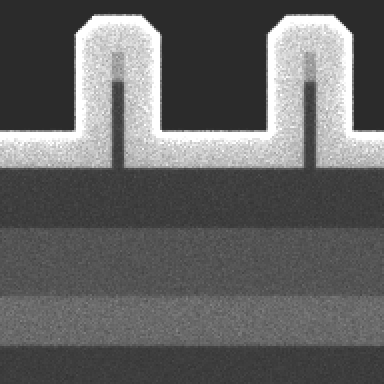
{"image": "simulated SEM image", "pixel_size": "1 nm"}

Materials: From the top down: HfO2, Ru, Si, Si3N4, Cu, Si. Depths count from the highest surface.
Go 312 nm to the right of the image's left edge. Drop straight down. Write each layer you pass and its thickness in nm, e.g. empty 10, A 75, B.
HfO2 36, Ru 30, Si 146, Si3N4 68, Cu 50, Si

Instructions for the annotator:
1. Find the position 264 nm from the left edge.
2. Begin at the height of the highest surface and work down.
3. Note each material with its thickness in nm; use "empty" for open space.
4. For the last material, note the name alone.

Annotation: empty 116, HfO2 36, Si 60, Si3N4 68, Cu 50, Si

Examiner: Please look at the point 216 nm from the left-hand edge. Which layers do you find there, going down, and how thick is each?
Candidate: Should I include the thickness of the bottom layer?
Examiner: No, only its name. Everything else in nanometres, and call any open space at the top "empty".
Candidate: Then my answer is empty 116, HfO2 36, Si 60, Si3N4 68, Cu 50, Si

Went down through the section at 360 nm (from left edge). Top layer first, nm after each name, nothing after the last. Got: empty 116, HfO2 36, Si 60, Si3N4 68, Cu 50, Si